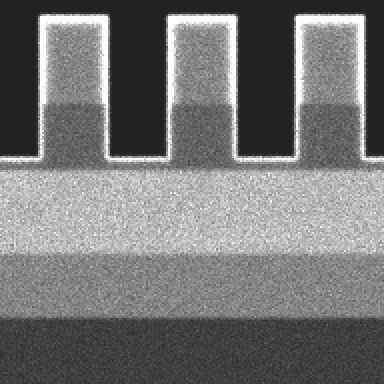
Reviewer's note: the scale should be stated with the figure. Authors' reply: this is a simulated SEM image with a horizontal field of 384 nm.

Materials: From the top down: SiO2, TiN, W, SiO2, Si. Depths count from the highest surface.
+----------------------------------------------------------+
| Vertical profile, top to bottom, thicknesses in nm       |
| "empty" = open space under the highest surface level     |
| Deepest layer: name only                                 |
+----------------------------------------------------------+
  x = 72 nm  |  SiO2 88, TiN 66, W 84, SiO2 64, Si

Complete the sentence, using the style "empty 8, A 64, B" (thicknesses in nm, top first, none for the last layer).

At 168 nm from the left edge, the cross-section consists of SiO2 88, TiN 66, W 84, SiO2 64, Si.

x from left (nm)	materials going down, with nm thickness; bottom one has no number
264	empty 142, TiN 12, W 84, SiO2 64, Si